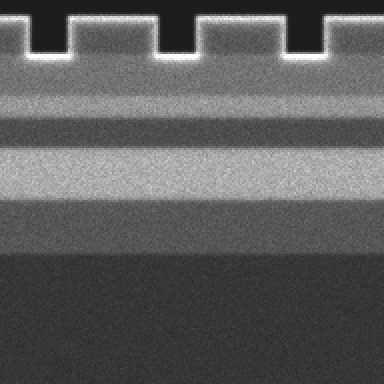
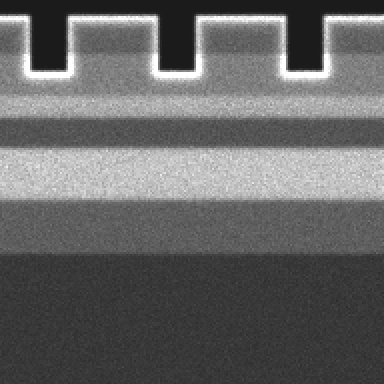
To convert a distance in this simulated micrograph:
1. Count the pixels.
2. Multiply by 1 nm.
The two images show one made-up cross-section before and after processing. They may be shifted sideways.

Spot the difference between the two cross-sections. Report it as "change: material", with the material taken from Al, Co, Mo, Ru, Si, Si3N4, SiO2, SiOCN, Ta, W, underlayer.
removed: SiO2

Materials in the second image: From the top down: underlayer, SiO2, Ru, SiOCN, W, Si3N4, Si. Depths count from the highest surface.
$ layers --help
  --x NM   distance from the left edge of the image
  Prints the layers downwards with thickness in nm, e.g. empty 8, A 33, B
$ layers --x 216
underlayer 38, SiO2 42, Ru 22, SiOCN 30, W 52, Si3N4 54, Si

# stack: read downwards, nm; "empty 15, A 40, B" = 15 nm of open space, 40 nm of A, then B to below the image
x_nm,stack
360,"underlayer 38, SiO2 42, Ru 22, SiOCN 30, W 52, Si3N4 54, Si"